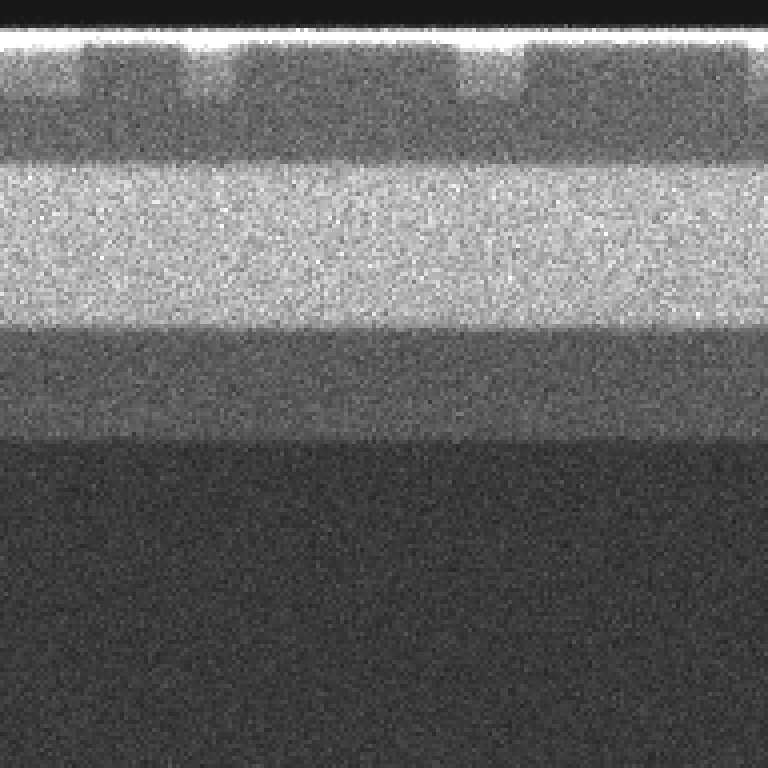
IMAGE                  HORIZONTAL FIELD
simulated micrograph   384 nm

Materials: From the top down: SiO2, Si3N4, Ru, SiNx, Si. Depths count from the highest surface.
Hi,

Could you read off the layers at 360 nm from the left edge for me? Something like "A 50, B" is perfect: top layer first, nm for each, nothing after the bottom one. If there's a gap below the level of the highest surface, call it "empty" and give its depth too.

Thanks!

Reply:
Si3N4 66, Ru 82, SiNx 56, Si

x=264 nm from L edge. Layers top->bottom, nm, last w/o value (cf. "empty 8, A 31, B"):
Si3N4 66, Ru 82, SiNx 56, Si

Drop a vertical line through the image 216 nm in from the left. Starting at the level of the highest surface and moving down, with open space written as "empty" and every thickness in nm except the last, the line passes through Si3N4 66, Ru 82, SiNx 56, Si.